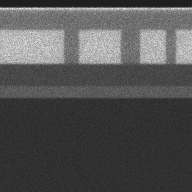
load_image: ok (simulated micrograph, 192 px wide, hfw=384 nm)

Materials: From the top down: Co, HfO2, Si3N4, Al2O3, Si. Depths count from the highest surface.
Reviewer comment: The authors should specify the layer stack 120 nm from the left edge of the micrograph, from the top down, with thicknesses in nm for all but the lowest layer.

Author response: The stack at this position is Co 44, HfO2 68, Si3N4 44, Al2O3 24, Si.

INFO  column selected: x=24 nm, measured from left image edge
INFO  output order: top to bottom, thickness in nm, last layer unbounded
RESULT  Co 44, HfO2 68, Si3N4 44, Al2O3 24, Si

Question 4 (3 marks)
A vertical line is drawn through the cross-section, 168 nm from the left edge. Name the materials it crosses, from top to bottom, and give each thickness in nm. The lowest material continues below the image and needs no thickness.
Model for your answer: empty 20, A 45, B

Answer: Co 44, HfO2 68, Si3N4 44, Al2O3 24, Si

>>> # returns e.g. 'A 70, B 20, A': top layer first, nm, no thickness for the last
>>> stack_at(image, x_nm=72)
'Co 44, HfO2 68, Si3N4 44, Al2O3 24, Si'